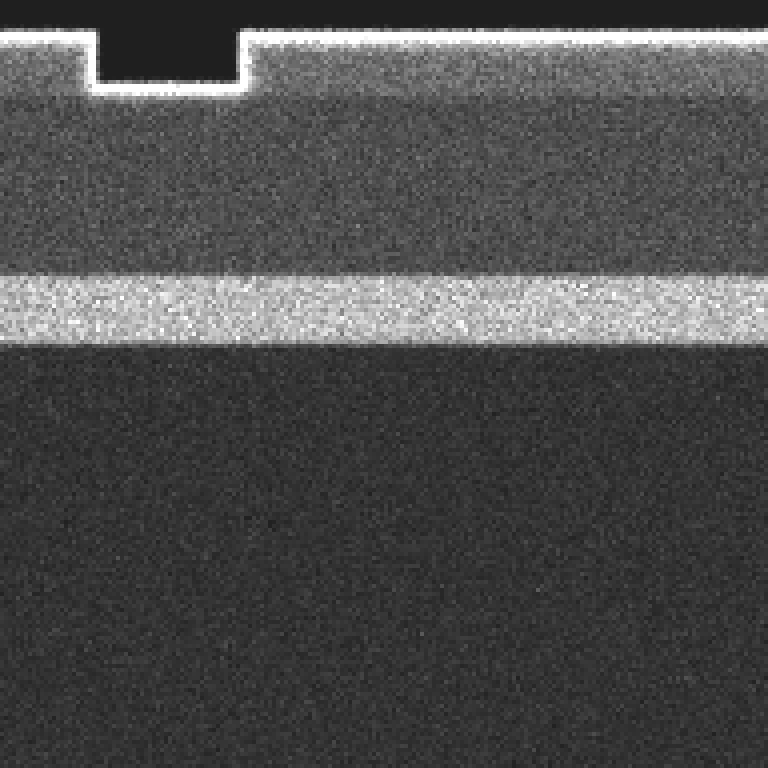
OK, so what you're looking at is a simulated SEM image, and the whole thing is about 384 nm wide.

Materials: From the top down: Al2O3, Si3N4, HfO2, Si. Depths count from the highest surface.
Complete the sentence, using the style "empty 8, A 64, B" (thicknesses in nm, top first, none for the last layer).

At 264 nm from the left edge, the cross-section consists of Al2O3 32, Si3N4 90, HfO2 34, Si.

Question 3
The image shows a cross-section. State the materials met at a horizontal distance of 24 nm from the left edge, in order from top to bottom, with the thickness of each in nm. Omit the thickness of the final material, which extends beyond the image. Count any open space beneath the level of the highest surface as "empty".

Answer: Al2O3 32, Si3N4 90, HfO2 34, Si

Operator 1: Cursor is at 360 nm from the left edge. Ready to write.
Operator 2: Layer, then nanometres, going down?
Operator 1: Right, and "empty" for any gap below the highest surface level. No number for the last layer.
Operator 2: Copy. Al2O3 32, Si3N4 90, HfO2 34, Si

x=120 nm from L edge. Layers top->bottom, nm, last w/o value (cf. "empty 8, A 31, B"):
Al2O3 32, Si3N4 90, HfO2 34, Si